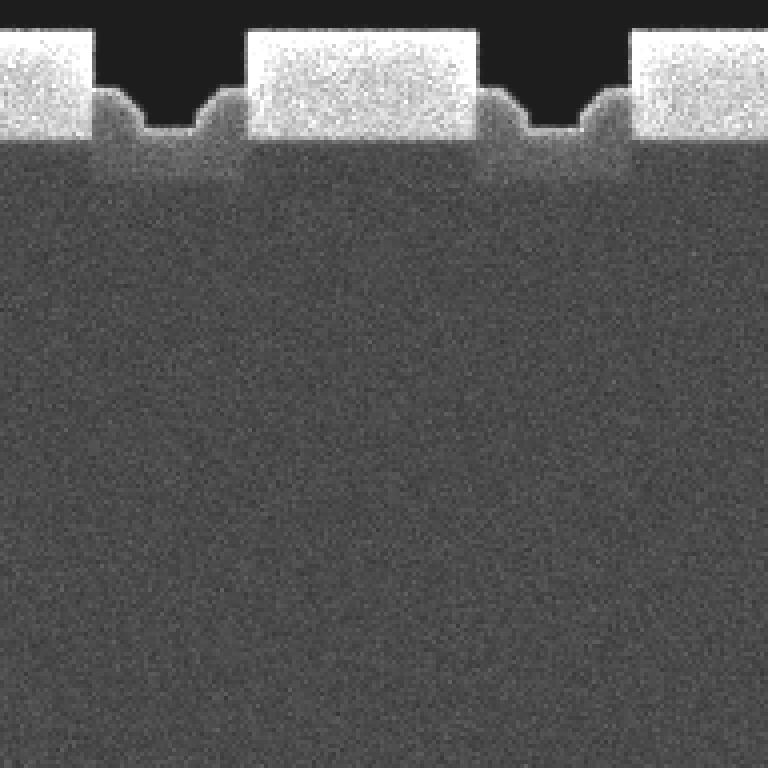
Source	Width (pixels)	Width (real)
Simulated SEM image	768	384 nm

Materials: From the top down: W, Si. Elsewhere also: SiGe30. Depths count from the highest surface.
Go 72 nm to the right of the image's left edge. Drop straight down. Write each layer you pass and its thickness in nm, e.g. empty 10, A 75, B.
empty 48, SiGe30 26, Si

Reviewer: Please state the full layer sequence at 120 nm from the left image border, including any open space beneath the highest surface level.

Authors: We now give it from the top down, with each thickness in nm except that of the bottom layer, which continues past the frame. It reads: empty 28, SiGe30 46, Si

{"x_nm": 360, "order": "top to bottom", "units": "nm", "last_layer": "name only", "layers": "W 54, Si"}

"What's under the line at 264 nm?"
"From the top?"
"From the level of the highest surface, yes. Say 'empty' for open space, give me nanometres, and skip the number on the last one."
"empty 48, SiGe30 26, Si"